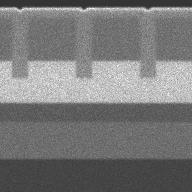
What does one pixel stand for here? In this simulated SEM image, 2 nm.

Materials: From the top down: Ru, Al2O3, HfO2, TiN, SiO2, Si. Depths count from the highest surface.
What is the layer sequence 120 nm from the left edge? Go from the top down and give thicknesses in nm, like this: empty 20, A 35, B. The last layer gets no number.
Ru 20, Al2O3 86, HfO2 84, TiN 38, SiO2 74, Si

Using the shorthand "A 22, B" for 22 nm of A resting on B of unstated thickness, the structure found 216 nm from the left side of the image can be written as Ru 20, Al2O3 86, HfO2 84, TiN 38, SiO2 74, Si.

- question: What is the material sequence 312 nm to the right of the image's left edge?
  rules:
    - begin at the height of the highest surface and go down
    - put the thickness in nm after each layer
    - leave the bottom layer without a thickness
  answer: Ru 20, Al2O3 86, HfO2 84, TiN 38, SiO2 74, Si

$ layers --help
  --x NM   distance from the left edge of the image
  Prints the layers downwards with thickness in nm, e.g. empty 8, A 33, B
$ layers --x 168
empty 4, Ru 136, HfO2 50, TiN 38, SiO2 74, Si